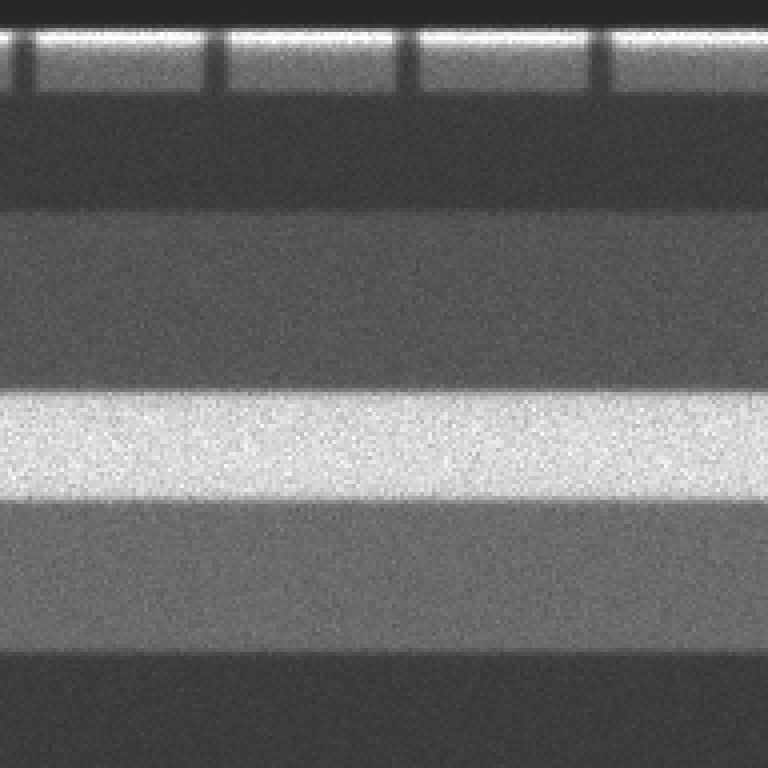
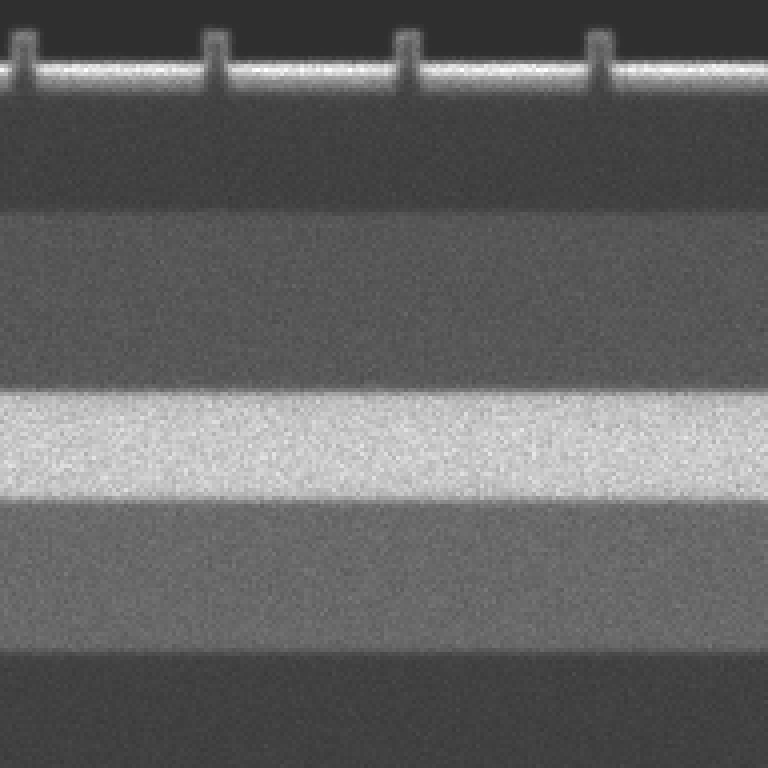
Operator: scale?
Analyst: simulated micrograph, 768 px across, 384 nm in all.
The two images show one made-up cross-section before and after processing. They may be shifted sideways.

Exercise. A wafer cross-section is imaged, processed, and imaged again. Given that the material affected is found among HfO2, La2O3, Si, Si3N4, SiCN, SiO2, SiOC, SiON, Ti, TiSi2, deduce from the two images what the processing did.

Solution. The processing removed SiO2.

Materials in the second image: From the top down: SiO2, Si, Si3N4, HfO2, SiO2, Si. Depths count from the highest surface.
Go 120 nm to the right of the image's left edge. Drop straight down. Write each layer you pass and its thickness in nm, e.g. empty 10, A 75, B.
empty 16, SiO2 14, Si 60, Si3N4 90, HfO2 54, SiO2 76, Si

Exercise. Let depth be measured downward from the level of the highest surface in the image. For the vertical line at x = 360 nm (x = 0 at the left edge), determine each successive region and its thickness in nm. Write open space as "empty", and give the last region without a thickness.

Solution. empty 16, SiO2 14, Si 60, Si3N4 90, HfO2 54, SiO2 76, Si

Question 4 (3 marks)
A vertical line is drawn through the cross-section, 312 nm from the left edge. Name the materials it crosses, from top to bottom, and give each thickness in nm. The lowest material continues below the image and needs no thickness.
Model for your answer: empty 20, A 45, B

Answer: empty 16, SiO2 14, Si 60, Si3N4 90, HfO2 54, SiO2 76, Si